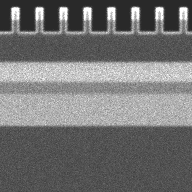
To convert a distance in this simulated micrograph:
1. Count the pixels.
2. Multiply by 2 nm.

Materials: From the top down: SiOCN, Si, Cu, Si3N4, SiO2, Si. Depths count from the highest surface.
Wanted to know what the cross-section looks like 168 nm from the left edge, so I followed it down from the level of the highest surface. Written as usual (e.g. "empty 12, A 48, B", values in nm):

SiOCN 24, Si 84, Cu 40, Si3N4 24, SiO2 64, Si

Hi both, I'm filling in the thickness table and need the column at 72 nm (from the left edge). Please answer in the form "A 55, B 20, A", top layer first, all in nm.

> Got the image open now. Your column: SiOCN 24, Si 84, Cu 40, Si3N4 24, SiO2 64, Si